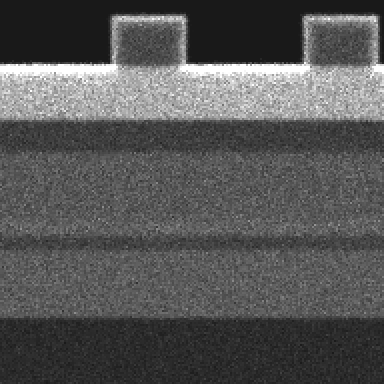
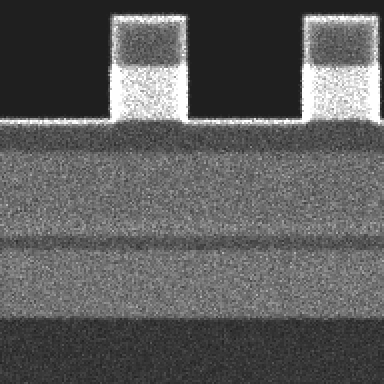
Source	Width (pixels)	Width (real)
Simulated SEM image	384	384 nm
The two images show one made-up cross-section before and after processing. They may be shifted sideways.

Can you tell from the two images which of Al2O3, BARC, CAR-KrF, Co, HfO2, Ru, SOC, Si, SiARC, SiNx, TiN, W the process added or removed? Yes, it removed HfO2.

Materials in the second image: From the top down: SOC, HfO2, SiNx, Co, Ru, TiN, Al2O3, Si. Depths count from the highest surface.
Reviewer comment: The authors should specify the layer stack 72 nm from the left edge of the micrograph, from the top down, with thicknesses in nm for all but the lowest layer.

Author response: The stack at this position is empty 104, SiNx 32, Co 68, Ru 16, TiN 14, Al2O3 68, Si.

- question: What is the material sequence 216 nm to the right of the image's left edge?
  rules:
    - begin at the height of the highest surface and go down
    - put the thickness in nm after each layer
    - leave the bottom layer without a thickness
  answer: empty 104, SiNx 32, Co 68, Ru 16, TiN 14, Al2O3 68, Si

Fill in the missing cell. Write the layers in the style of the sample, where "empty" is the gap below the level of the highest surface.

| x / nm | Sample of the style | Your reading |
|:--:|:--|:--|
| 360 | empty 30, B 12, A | SOC 50, HfO2 54, SiNx 32, Co 68, Ru 16, TiN 14, Al2O3 68, Si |